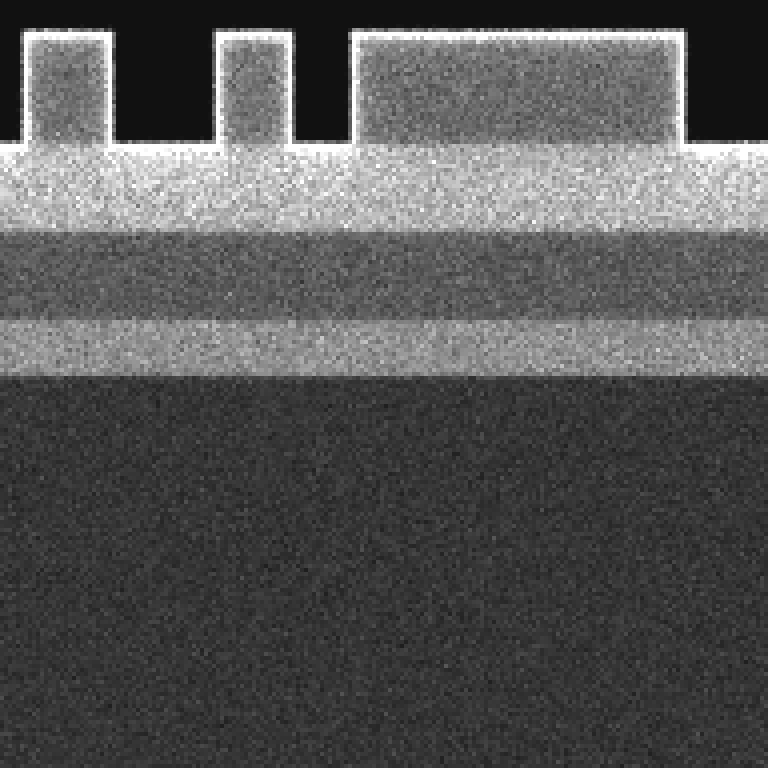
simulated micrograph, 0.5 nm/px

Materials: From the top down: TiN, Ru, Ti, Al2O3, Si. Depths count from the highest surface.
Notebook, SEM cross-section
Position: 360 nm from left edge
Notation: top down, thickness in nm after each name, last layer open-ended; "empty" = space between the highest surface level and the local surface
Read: empty 56, Ru 44, Ti 44, Al2O3 28, Si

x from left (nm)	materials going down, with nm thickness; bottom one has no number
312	TiN 56, Ru 44, Ti 44, Al2O3 28, Si